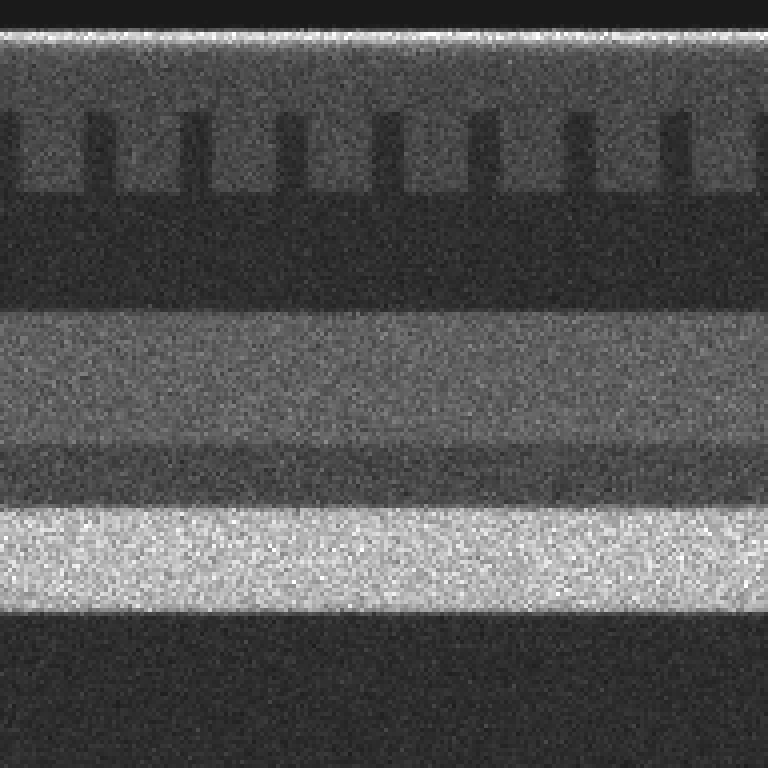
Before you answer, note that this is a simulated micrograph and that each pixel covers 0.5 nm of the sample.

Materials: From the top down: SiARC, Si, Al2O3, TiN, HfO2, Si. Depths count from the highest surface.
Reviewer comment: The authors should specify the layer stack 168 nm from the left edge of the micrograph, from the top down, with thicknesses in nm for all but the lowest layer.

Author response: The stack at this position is SiARC 80, Si 60, Al2O3 66, TiN 32, HfO2 52, Si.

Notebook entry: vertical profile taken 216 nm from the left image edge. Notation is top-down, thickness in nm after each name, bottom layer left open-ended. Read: SiARC 80, Si 60, Al2O3 66, TiN 32, HfO2 52, Si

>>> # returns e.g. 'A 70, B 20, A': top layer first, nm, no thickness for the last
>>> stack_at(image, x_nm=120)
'SiARC 80, Si 60, Al2O3 66, TiN 32, HfO2 52, Si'